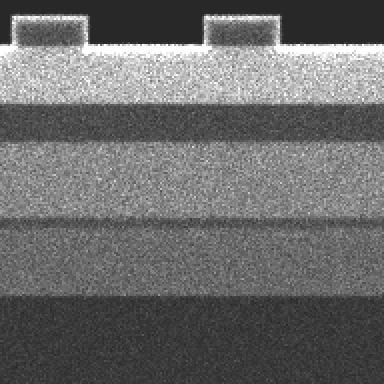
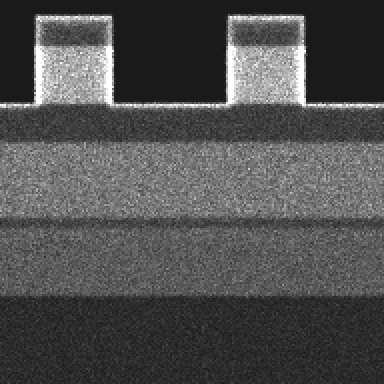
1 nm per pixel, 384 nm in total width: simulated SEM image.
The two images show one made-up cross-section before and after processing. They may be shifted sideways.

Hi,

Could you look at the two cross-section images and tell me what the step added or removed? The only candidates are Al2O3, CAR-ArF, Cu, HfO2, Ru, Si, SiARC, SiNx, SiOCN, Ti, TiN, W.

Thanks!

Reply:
removed HfO2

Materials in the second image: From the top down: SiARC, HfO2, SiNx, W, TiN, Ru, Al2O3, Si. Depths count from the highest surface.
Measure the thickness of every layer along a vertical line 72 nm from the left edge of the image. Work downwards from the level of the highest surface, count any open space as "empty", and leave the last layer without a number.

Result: SiARC 30, HfO2 58, SiNx 38, W 76, TiN 10, Ru 12, Al2O3 56, Si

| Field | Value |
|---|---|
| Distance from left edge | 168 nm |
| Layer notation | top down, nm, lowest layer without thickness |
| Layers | empty 88, SiNx 38, W 76, TiN 10, Ru 12, Al2O3 56, Si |